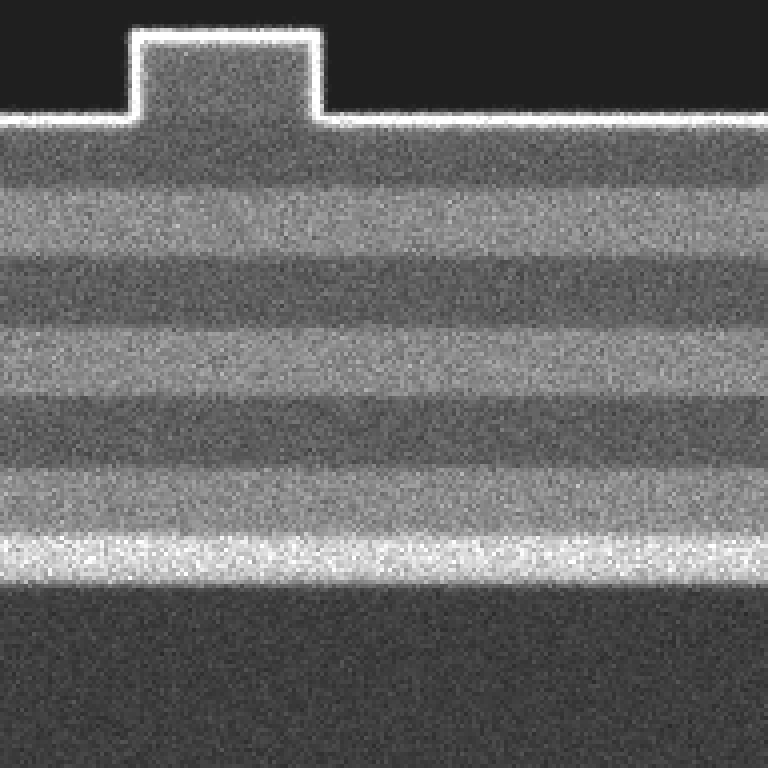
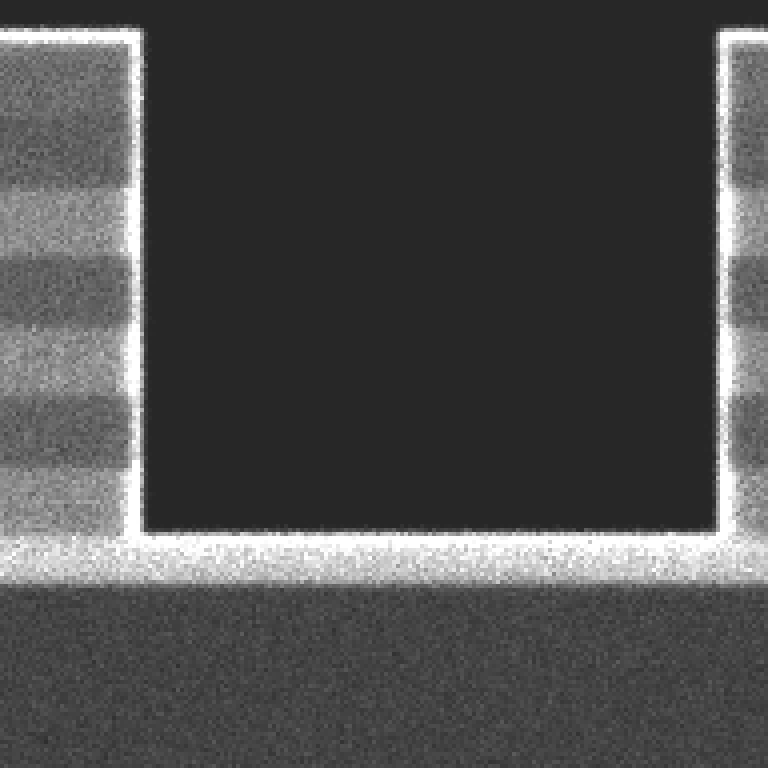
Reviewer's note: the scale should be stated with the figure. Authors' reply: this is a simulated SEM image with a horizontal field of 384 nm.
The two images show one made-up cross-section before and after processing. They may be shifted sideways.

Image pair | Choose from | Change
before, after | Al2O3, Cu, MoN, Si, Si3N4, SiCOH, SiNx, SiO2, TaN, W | SiNx and SiO2 (removed)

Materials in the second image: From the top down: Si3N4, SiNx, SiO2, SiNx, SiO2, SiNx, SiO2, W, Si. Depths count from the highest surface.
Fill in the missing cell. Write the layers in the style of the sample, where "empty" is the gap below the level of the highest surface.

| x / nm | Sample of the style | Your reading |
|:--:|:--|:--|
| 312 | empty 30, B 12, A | empty 252, W 24, Si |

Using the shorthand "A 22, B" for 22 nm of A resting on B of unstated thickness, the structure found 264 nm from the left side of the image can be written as empty 252, W 24, Si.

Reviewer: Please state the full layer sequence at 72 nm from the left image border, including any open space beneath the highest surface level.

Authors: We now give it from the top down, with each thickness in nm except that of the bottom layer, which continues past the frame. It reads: empty 252, W 24, Si